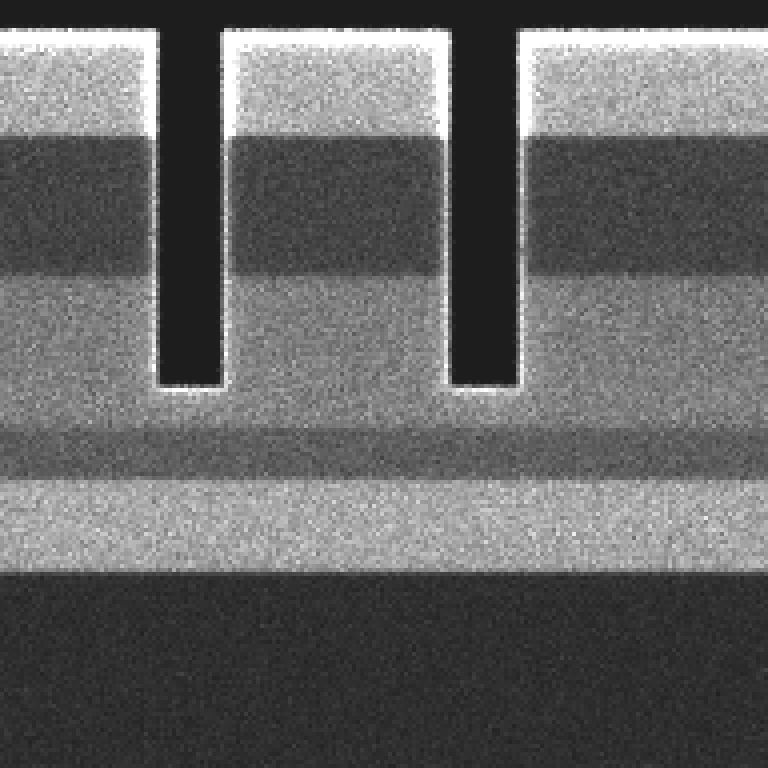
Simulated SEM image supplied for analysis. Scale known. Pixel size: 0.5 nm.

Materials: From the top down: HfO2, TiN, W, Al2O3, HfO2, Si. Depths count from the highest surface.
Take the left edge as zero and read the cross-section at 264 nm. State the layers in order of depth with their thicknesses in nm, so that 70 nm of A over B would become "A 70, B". HfO2 52, TiN 70, W 76, Al2O3 26, HfO2 46, Si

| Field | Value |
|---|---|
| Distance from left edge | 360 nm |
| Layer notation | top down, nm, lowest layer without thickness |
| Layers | HfO2 52, TiN 70, W 76, Al2O3 26, HfO2 46, Si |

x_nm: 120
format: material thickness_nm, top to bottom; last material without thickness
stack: HfO2 52, TiN 70, W 76, Al2O3 26, HfO2 46, Si